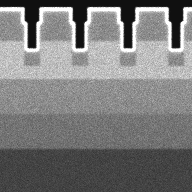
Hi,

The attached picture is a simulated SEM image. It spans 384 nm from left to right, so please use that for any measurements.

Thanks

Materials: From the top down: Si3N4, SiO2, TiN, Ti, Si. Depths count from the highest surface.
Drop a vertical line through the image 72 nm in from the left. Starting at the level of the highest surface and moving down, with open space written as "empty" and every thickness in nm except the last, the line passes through empty 82, Si3N4 34, SiO2 26, TiN 70, Ti 70, Si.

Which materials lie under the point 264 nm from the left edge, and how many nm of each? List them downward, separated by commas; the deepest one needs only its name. empty 82, Si3N4 34, SiO2 26, TiN 70, Ti 70, Si